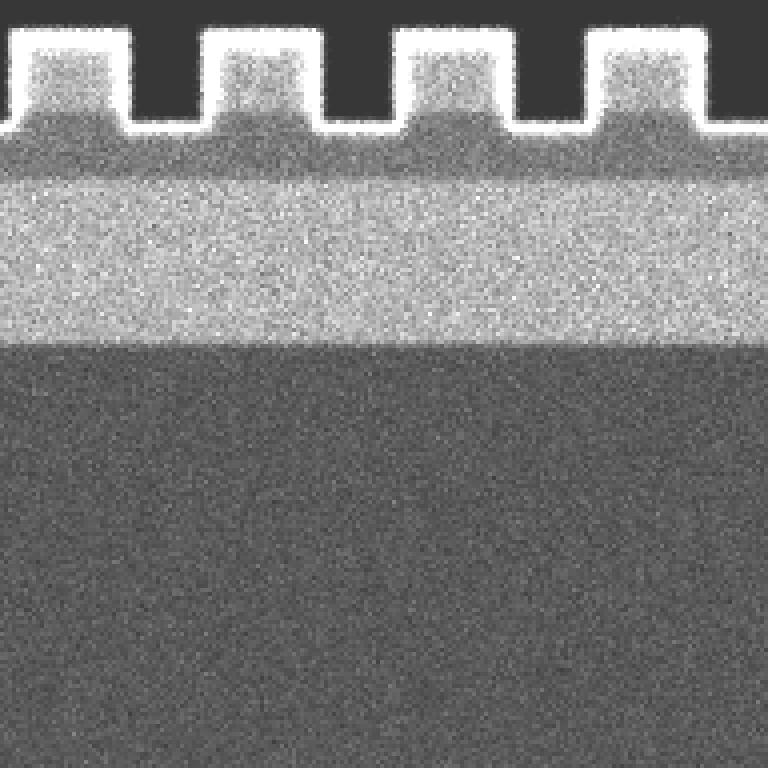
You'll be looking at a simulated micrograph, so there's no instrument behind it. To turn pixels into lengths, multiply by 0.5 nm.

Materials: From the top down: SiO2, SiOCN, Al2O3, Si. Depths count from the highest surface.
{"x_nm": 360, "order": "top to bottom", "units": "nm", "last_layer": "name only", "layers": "empty 46, SiOCN 28, Al2O3 82, Si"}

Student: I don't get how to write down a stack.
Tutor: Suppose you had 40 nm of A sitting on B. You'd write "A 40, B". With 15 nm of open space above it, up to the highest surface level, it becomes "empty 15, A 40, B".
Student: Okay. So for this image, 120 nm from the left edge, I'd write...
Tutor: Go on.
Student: SiO2 40, SiOCN 34, Al2O3 82, Si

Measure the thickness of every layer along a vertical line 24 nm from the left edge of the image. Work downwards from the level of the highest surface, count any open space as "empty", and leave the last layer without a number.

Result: SiO2 40, SiOCN 34, Al2O3 82, Si